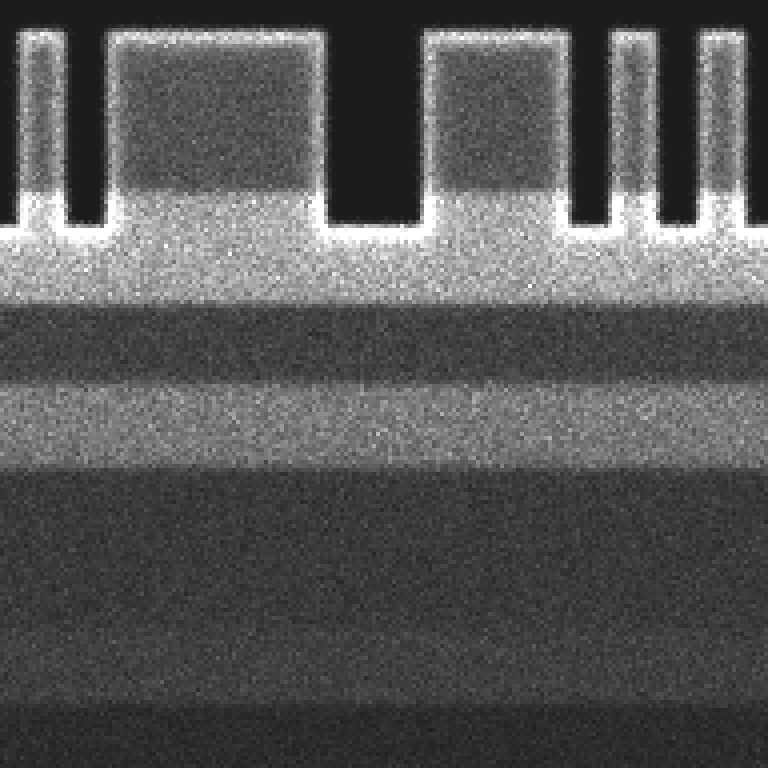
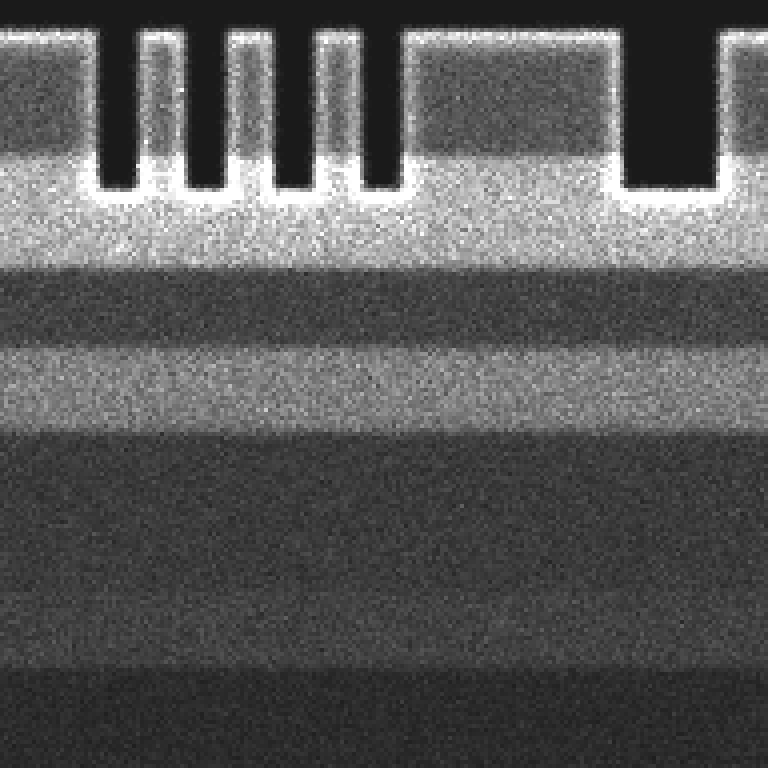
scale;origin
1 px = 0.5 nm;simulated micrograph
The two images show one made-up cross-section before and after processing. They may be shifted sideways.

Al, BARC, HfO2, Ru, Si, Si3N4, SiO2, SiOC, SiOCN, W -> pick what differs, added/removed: SiO2 removed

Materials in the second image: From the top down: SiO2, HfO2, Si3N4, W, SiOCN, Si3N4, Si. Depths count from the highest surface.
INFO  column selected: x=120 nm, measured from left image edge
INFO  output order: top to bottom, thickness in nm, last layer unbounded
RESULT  SiO2 62, HfO2 56, Si3N4 40, W 42, SiOCN 80, Si3N4 38, Si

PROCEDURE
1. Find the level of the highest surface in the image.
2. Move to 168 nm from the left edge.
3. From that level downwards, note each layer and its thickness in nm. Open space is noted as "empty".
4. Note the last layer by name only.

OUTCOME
SiO2 62, HfO2 56, Si3N4 40, W 42, SiOCN 80, Si3N4 38, Si